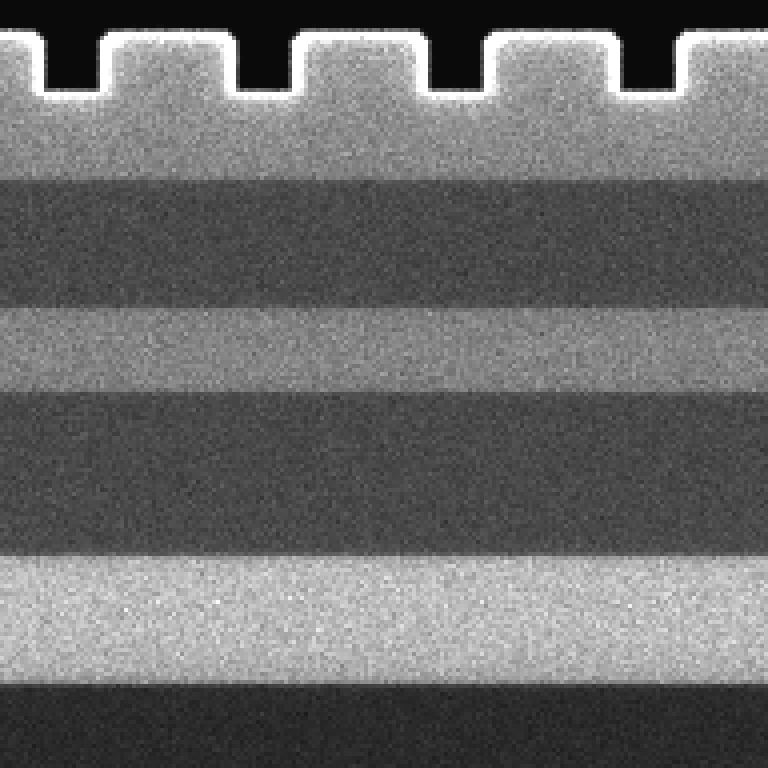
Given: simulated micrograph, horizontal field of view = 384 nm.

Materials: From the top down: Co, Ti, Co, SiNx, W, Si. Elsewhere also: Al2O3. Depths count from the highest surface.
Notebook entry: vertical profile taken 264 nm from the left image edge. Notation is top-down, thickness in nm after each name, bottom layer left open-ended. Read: Co 74, Ti 64, Co 42, SiNx 82, W 64, Si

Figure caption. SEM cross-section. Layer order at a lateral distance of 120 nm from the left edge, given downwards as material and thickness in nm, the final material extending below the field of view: empty 30, Co 44, Ti 64, Co 42, SiNx 82, W 64, Si